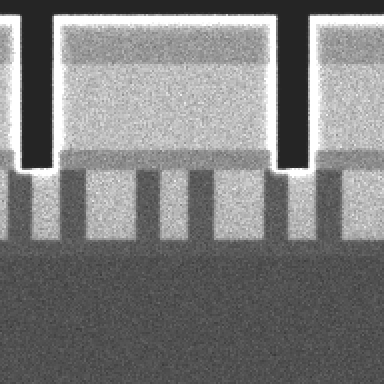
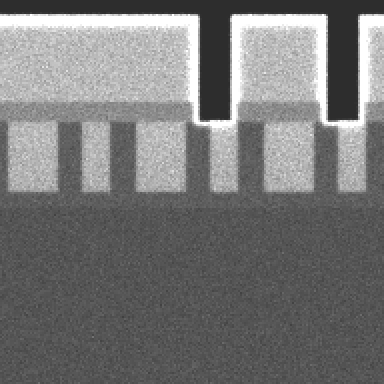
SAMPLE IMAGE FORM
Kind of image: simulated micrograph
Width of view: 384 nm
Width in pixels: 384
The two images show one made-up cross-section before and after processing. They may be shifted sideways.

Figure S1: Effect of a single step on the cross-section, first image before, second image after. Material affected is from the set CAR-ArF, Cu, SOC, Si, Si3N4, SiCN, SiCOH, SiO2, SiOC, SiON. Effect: removed SOC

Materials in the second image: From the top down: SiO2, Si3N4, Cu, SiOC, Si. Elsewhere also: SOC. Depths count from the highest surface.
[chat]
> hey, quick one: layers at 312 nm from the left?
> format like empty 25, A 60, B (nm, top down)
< SiO2 86, Si3N4 20, Cu 70, SiOC 16, Si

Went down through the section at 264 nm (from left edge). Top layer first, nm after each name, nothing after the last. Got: SiO2 86, Si3N4 20, Cu 70, SiOC 16, Si